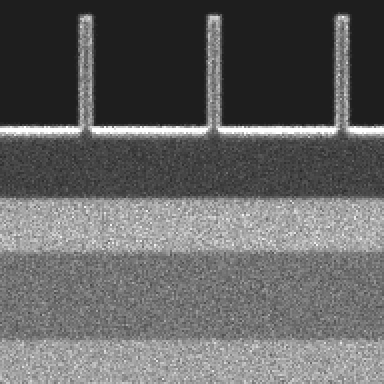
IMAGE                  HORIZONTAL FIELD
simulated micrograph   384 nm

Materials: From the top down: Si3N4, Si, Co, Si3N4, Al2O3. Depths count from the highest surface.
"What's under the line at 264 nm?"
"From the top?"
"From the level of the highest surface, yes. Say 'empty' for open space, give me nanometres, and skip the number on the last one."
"empty 112, Si3N4 10, Si 60, Co 54, Si3N4 88, Al2O3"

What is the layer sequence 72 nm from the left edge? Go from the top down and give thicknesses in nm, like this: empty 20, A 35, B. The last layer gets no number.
empty 112, Si3N4 10, Si 60, Co 54, Si3N4 88, Al2O3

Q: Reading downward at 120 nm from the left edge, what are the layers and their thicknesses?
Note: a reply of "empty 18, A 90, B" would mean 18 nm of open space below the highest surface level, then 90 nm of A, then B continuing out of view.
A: empty 112, Si3N4 10, Si 60, Co 54, Si3N4 88, Al2O3